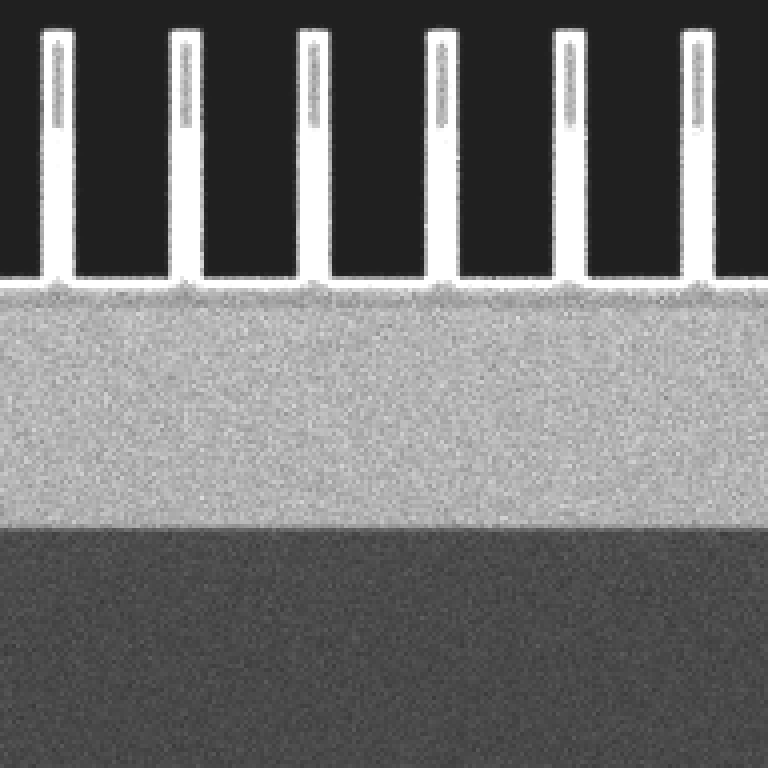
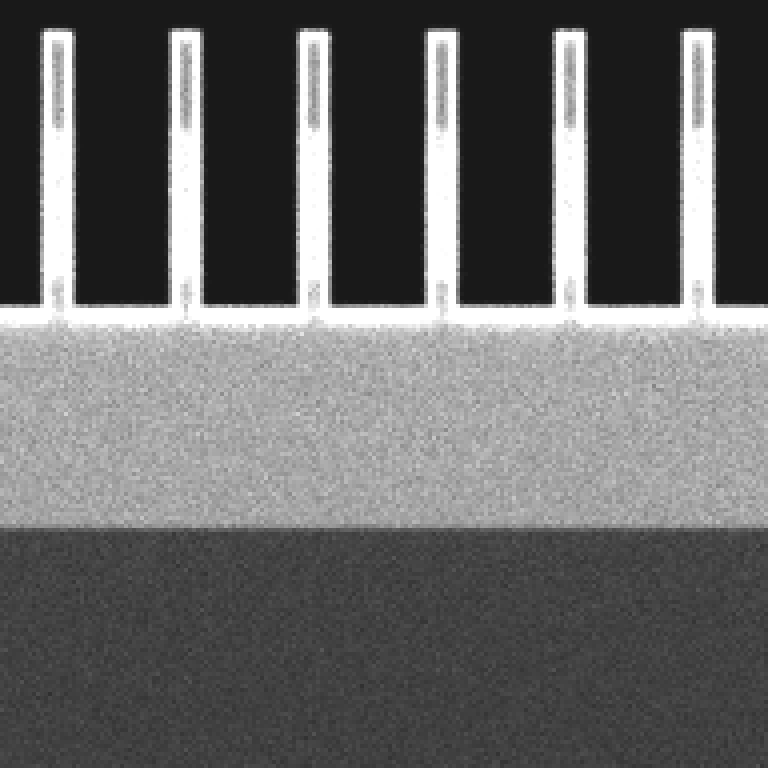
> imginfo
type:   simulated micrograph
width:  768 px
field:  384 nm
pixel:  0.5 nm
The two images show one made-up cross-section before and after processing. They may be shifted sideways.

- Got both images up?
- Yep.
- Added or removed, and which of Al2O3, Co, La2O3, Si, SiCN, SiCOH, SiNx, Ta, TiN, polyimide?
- removed, TiN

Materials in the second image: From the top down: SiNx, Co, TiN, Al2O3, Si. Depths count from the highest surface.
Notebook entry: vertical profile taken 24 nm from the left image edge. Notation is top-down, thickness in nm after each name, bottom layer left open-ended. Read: SiNx 48, Co 76, TiN 14, Al2O3 110, Si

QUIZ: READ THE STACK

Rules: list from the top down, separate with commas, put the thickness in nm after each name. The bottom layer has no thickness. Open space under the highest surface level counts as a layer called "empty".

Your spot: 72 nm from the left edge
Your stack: empty 138, Al2O3 110, Si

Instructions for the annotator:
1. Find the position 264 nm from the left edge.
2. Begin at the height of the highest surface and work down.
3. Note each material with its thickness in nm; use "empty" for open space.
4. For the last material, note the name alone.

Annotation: empty 138, Al2O3 110, Si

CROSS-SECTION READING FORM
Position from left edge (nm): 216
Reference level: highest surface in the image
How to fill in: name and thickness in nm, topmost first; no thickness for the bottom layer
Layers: SiNx 48, Co 76, TiN 14, Al2O3 110, Si